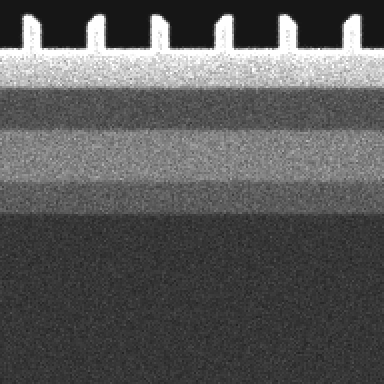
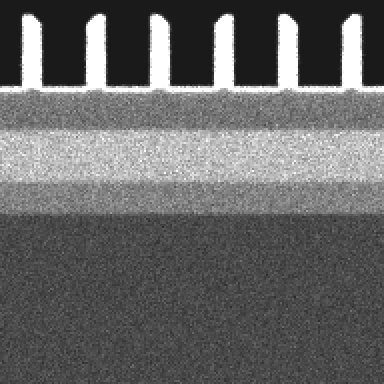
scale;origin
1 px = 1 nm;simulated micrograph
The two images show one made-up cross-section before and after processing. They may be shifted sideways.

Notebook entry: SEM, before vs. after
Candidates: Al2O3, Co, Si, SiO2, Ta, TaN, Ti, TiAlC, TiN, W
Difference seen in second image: W removed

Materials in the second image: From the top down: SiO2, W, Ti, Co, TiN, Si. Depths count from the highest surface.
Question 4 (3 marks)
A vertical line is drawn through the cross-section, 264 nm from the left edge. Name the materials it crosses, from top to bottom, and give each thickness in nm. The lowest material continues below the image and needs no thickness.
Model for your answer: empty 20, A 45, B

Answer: empty 72, Ti 42, Co 52, TiN 32, Si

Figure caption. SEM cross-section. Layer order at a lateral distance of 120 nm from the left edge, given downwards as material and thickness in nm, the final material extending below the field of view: empty 72, Ti 42, Co 52, TiN 32, Si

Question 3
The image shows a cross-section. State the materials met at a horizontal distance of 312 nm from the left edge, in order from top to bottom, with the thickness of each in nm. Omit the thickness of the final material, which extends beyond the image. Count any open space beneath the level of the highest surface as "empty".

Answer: empty 72, Ti 42, Co 52, TiN 32, Si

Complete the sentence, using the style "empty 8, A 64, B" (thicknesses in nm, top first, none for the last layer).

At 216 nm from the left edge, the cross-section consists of empty 8, SiO2 26, W 38, Ti 42, Co 52, TiN 32, Si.